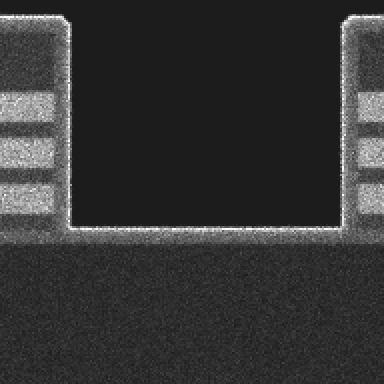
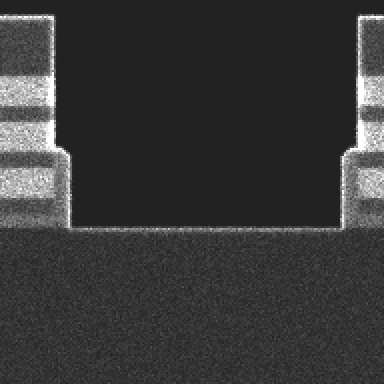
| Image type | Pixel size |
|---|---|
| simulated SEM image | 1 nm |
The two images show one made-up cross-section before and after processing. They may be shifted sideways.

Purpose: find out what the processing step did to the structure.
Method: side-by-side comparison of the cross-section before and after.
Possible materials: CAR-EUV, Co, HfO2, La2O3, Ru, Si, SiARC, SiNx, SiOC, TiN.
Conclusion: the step removed Co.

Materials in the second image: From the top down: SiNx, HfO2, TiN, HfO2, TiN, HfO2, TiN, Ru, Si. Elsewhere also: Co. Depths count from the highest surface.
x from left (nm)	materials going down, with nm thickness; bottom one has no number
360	SiNx 60, HfO2 30, TiN 16, HfO2 30, TiN 16, HfO2 30, TiN 16, Ru 14, Si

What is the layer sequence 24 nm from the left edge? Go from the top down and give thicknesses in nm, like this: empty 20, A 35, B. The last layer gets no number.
SiNx 60, HfO2 30, TiN 16, HfO2 30, TiN 16, HfO2 30, TiN 16, Ru 14, Si